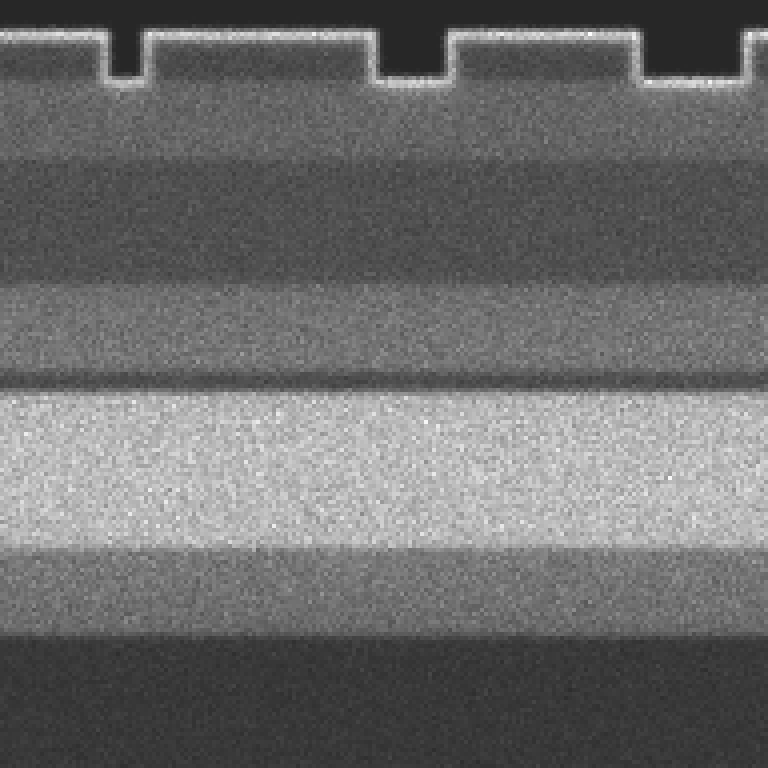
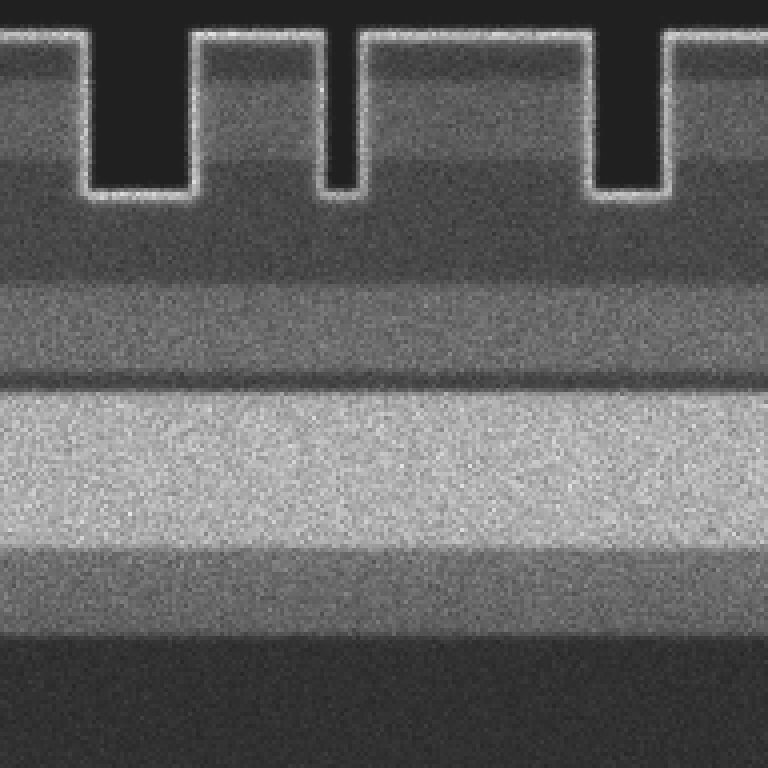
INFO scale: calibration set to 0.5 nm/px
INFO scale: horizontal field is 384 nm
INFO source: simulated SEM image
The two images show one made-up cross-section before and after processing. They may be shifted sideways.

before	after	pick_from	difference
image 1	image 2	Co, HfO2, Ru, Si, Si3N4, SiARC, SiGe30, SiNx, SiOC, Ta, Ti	Co and Si3N4 removed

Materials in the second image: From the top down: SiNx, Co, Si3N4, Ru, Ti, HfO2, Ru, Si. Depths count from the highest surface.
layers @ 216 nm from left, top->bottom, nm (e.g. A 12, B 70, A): SiNx 24, Co 40, Si3N4 62, Ru 44, Ti 10, HfO2 78, Ru 44, Si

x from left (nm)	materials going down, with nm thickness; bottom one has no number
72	empty 80, Si3N4 46, Ru 44, Ti 10, HfO2 78, Ru 44, Si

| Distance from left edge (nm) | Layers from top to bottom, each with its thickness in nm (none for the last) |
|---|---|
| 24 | SiNx 24, Co 40, Si3N4 62, Ru 44, Ti 10, HfO2 78, Ru 44, Si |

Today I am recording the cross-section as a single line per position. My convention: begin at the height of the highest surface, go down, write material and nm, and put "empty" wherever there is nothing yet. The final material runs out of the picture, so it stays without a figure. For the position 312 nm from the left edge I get empty 80, Si3N4 46, Ru 44, Ti 10, HfO2 78, Ru 44, Si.